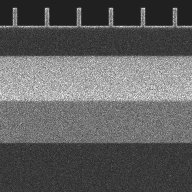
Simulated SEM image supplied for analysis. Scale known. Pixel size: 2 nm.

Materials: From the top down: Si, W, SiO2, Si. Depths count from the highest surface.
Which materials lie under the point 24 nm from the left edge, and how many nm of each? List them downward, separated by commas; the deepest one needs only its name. empty 36, Si 60, W 90, SiO2 84, Si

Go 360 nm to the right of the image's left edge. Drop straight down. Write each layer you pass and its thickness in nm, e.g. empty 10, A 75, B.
empty 36, Si 60, W 90, SiO2 84, Si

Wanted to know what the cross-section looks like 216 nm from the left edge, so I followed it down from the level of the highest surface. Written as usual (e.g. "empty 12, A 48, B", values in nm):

empty 36, Si 60, W 90, SiO2 84, Si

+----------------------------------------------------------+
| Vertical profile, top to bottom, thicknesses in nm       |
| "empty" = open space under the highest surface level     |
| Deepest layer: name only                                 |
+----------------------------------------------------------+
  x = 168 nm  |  empty 36, Si 60, W 90, SiO2 84, Si